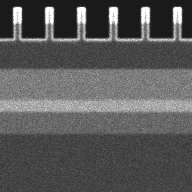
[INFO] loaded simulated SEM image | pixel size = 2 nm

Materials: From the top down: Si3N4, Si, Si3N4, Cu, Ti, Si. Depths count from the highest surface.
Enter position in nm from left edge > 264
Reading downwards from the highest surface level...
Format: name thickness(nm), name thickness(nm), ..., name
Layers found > empty 62, Si 60, Si3N4 62, Cu 24, Ti 44, Si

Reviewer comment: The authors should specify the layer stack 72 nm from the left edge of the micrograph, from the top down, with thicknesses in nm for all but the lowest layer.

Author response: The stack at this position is empty 62, Si 60, Si3N4 62, Cu 24, Ti 44, Si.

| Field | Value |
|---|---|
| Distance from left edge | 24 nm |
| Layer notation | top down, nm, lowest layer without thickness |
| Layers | empty 62, Si 60, Si3N4 62, Cu 24, Ti 44, Si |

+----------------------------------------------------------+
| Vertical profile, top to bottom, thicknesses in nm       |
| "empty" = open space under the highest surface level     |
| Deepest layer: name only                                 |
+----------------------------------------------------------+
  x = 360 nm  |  Si3N4 30, Si 92, Si3N4 62, Cu 24, Ti 44, Si